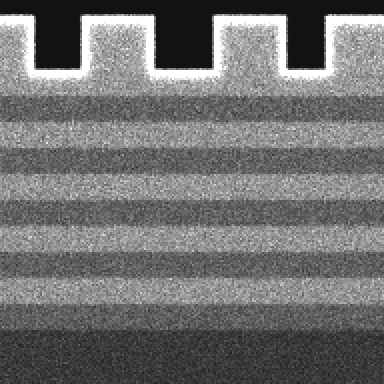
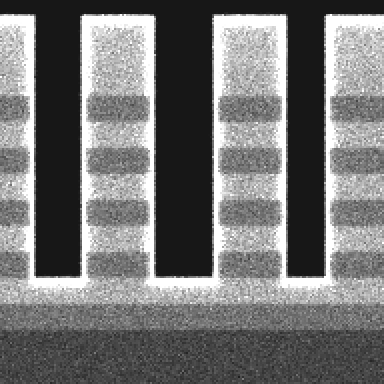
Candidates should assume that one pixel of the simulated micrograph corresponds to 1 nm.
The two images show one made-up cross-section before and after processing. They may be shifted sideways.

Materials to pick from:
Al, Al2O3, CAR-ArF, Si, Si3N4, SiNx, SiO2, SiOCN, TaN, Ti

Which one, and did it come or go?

SiNx and SiO2 - removed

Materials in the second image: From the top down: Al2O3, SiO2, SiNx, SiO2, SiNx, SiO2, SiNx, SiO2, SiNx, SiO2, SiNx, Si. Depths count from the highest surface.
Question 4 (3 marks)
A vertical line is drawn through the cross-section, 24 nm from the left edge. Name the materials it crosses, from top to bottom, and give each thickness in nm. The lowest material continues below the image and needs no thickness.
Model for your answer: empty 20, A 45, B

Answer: Al2O3 54, SiO2 26, SiNx 26, SiO2 26, SiNx 26, SiO2 26, SiNx 26, SiO2 26, SiNx 26, SiO2 26, SiNx 26, Si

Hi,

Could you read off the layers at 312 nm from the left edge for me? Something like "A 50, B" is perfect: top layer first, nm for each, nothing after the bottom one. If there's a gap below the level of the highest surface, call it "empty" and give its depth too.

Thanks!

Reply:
empty 262, SiO2 26, SiNx 26, Si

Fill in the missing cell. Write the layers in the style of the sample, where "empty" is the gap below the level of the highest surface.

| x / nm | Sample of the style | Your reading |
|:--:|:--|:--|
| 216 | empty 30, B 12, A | Al2O3 54, SiO2 26, SiNx 26, SiO2 26, SiNx 26, SiO2 26, SiNx 26, SiO2 26, SiNx 26, SiO2 26, SiNx 26, Si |